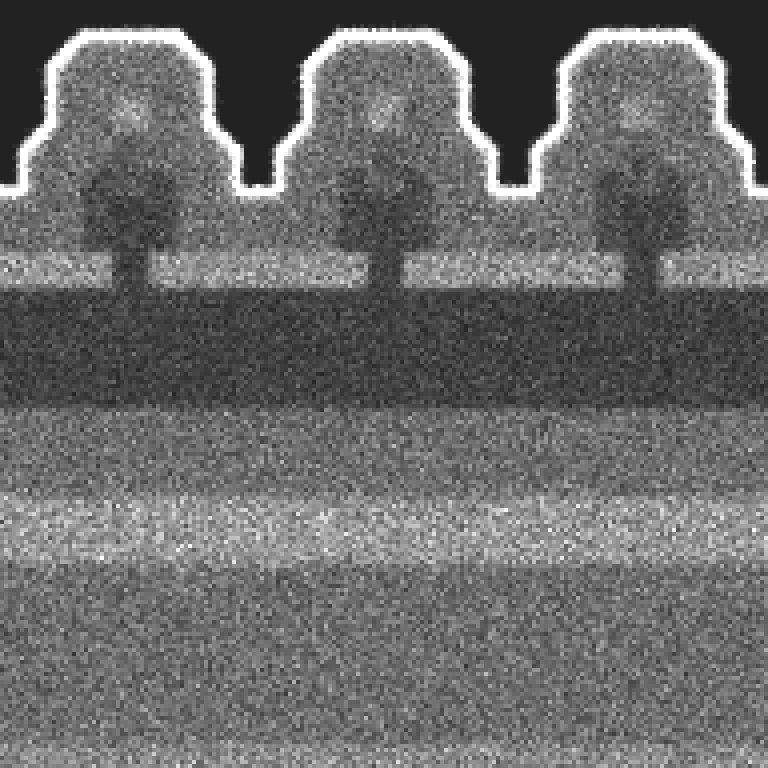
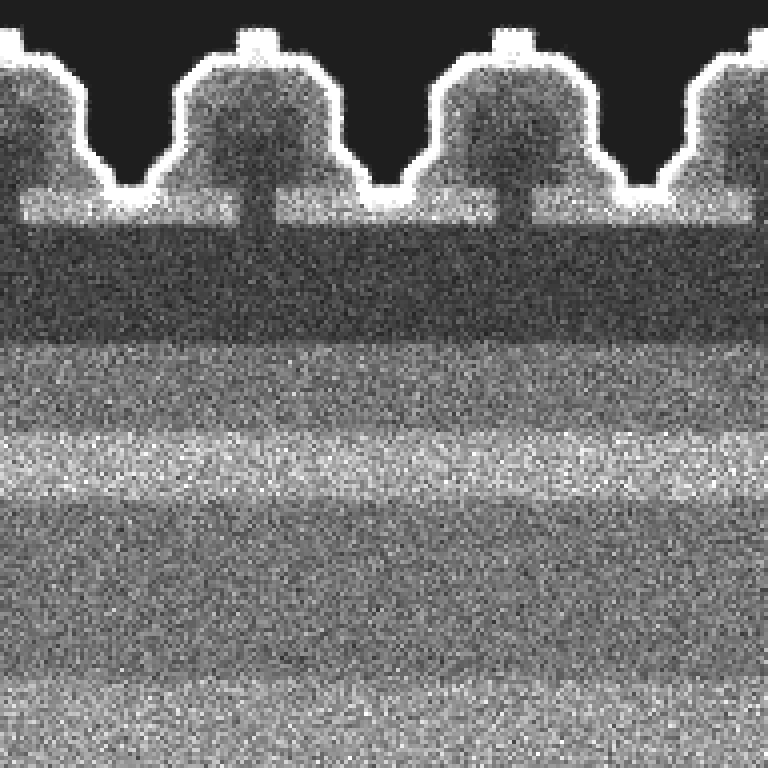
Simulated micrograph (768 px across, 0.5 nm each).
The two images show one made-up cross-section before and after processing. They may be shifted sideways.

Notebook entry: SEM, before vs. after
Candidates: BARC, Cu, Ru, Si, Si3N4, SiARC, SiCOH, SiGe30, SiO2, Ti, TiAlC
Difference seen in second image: Si3N4 removed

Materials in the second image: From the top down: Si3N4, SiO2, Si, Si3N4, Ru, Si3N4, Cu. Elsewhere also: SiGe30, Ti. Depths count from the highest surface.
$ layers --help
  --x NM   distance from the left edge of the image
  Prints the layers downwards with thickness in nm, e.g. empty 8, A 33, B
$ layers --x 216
empty 28, Si3N4 50, SiO2 18, Si 60, Si3N4 44, Ru 34, Si3N4 90, Cu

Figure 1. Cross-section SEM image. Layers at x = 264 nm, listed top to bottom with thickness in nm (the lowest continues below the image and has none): SiO2 18, Ti 32, Si 106, Si3N4 44, Ru 34, Si3N4 90, Cu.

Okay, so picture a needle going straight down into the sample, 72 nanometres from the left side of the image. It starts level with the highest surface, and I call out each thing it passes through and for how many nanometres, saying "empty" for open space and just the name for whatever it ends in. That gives empty 78, SiO2 18, Si 60, Si3N4 44, Ru 34, Si3N4 90, Cu